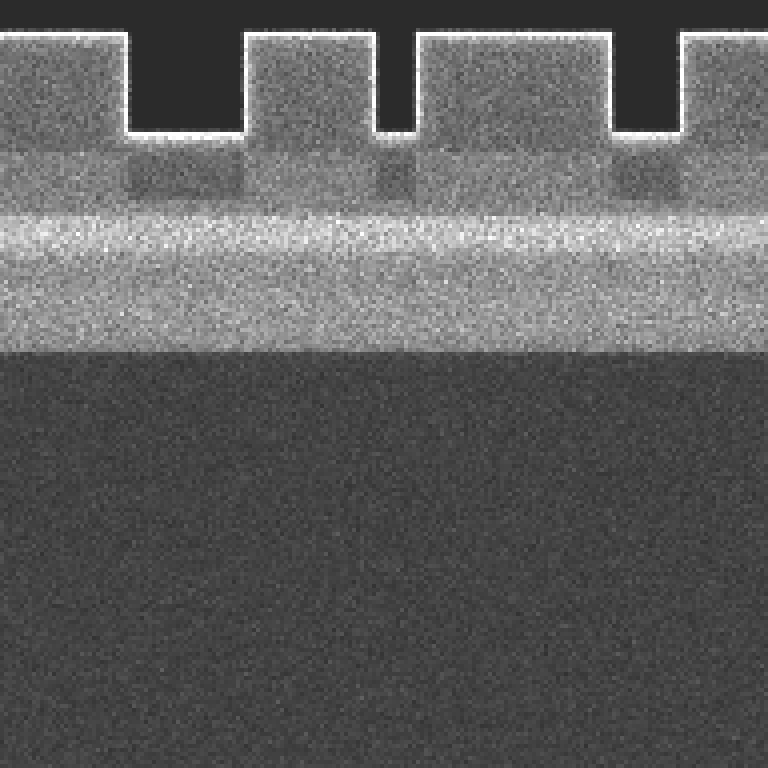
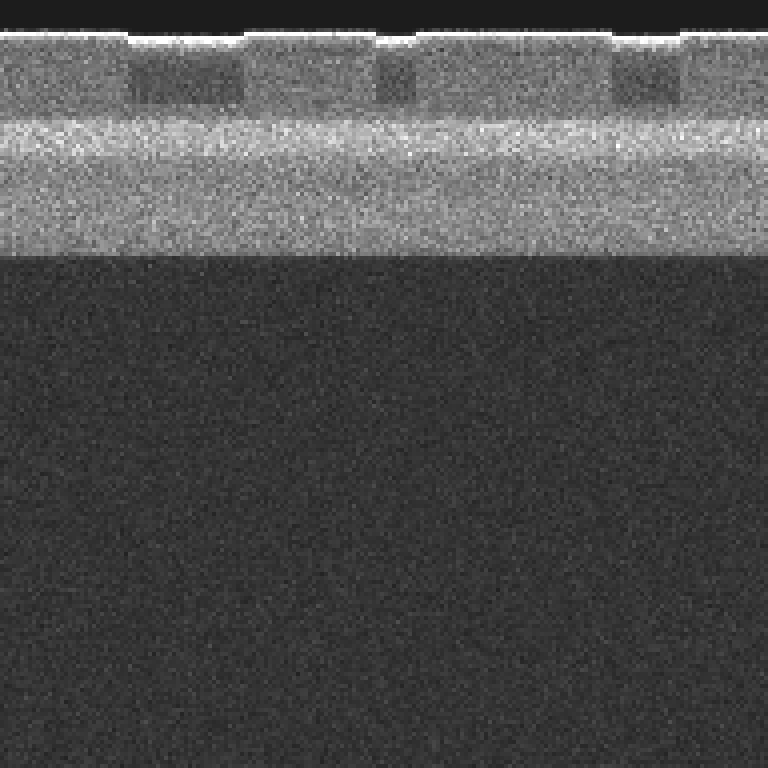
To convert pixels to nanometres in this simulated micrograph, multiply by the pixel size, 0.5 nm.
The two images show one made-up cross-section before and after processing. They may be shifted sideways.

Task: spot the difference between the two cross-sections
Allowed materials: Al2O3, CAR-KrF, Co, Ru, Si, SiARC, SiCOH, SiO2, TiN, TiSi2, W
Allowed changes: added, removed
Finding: removed TiN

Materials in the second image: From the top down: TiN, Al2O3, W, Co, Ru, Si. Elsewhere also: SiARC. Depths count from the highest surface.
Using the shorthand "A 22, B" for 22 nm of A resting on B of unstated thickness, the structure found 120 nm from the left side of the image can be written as empty 2, SiARC 34, Al2O3 8, W 18, Co 20, Ru 30, Si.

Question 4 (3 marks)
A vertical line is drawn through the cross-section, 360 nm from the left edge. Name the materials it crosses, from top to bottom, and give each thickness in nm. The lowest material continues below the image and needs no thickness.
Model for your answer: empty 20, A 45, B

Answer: TiN 12, Al2O3 32, W 18, Co 20, Ru 30, Si